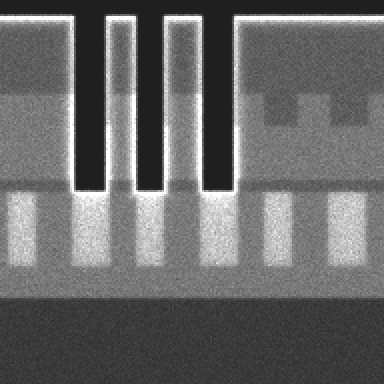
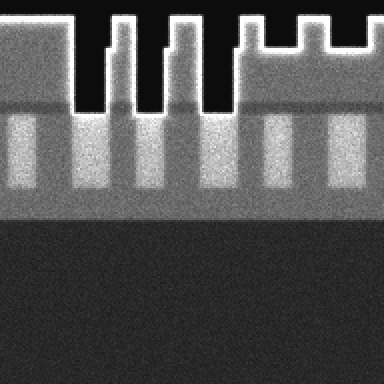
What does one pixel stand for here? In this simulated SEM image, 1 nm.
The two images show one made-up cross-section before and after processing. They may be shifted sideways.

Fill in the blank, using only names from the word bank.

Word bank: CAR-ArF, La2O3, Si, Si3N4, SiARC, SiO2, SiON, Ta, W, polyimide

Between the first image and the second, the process removed SiARC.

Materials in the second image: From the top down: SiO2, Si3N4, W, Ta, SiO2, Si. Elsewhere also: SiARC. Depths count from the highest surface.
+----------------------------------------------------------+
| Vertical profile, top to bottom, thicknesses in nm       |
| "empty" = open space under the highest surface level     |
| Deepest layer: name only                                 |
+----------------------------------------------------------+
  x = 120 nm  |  SiO2 86, Si3N4 12, SiO2 106, Si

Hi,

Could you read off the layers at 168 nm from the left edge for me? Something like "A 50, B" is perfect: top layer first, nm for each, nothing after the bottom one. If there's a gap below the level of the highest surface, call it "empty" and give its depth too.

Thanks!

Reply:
empty 32, SiO2 54, Si3N4 12, SiO2 106, Si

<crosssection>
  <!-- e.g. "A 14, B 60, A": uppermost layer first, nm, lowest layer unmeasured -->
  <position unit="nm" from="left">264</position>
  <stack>empty 32, SiO2 54, Si3N4 12, Ta 74, SiO2 32, Si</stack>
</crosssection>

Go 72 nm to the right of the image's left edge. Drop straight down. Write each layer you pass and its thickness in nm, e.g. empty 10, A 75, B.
SiO2 86, Si3N4 12, Ta 74, SiO2 32, Si